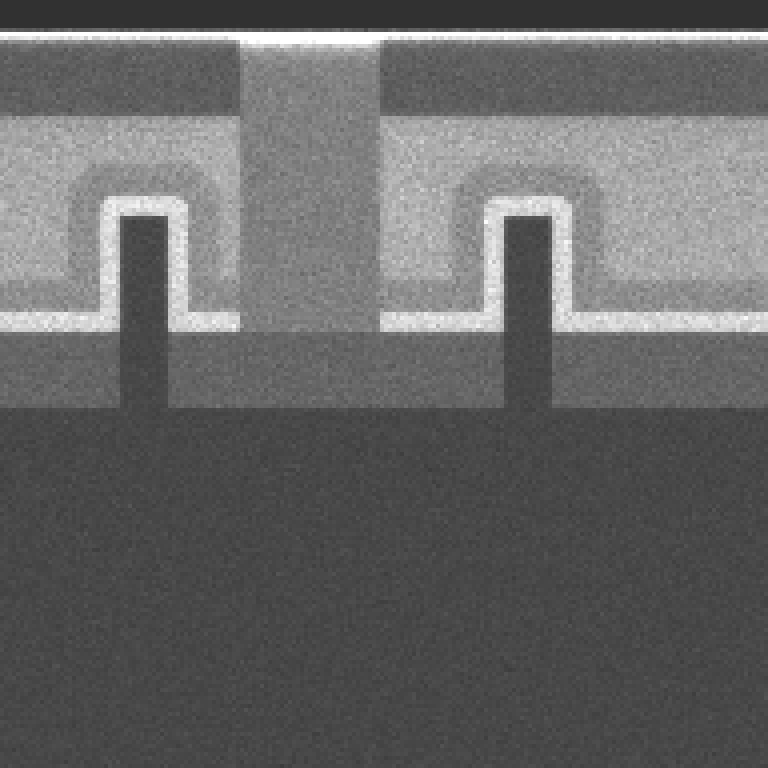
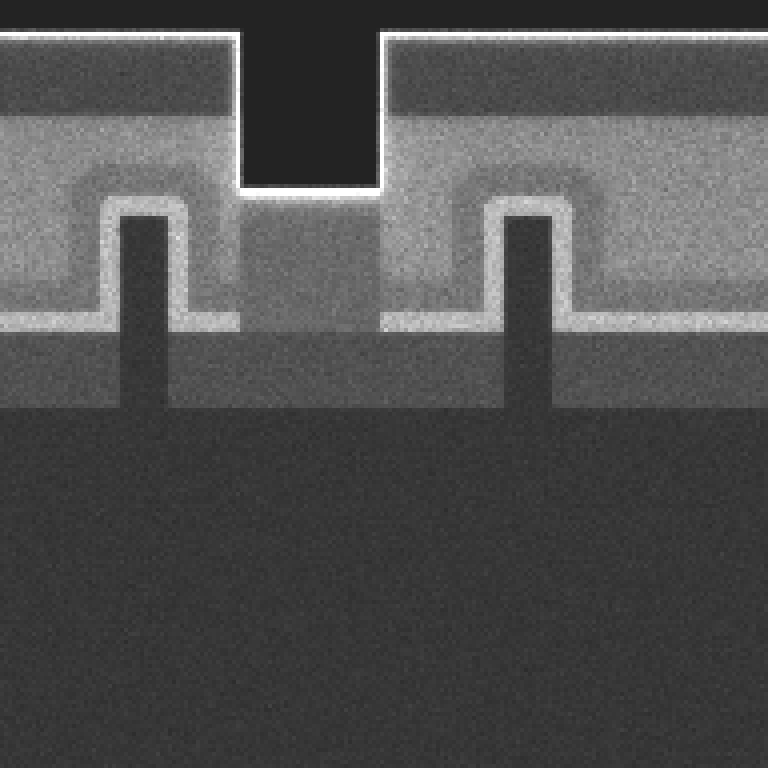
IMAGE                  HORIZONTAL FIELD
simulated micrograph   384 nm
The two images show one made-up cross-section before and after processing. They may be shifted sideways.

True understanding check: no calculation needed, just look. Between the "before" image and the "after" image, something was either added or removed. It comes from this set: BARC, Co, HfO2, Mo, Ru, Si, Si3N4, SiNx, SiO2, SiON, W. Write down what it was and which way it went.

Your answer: SiO2 (removed)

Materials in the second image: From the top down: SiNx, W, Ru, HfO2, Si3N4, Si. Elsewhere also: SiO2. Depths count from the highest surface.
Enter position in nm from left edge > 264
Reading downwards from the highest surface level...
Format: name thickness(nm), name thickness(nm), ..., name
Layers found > SiNx 42, W 24, Ru 16, HfO2 10, Si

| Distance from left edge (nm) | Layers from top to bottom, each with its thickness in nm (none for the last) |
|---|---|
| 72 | SiNx 42, W 24, Ru 16, HfO2 10, Si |